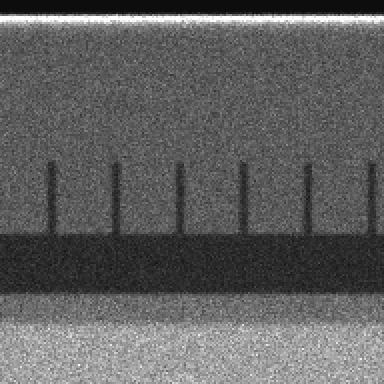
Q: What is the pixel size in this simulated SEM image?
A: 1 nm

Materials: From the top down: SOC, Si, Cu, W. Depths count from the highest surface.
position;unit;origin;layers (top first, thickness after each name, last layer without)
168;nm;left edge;SOC 218, Si 60, Cu 30, W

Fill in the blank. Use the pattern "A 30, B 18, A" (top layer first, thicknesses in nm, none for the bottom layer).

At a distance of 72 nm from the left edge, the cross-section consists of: SOC 218, Si 60, Cu 30, W